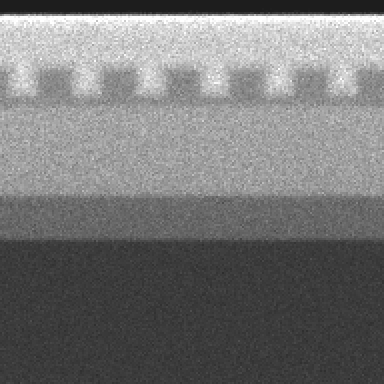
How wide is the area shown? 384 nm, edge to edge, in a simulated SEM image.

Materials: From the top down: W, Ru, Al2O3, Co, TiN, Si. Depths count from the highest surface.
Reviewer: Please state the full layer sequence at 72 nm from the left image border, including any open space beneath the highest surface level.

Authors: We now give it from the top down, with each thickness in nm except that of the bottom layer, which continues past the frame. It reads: W 46, Ru 34, Al2O3 10, Co 90, TiN 44, Si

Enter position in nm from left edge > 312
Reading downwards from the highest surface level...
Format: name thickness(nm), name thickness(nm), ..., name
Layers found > W 46, Ru 8, Al2O3 36, Co 90, TiN 44, Si